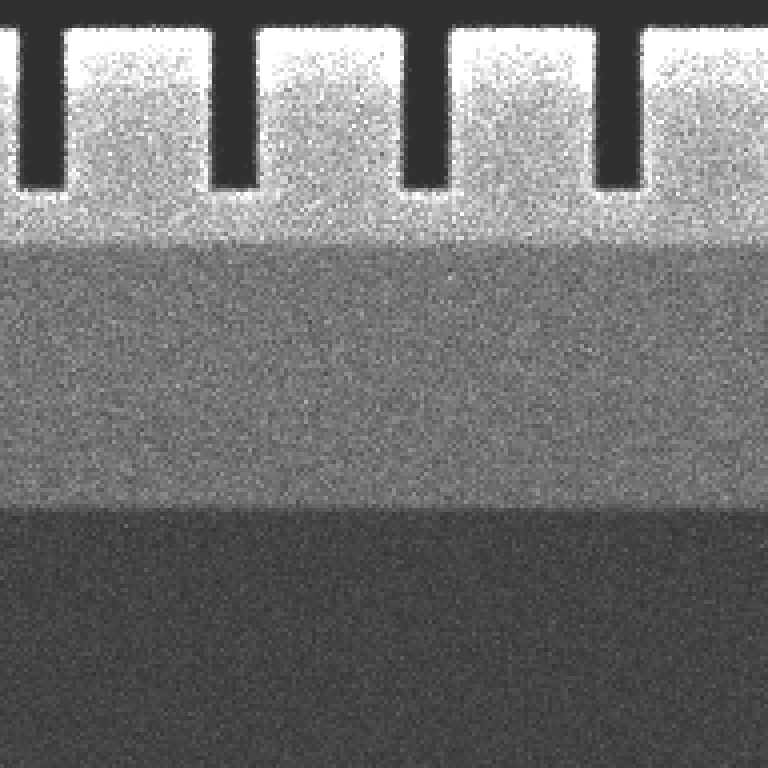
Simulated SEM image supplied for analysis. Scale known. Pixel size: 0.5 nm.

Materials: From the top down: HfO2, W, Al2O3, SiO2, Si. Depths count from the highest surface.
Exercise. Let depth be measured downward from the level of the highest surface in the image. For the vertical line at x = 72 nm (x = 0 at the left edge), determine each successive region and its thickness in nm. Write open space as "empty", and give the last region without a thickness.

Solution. HfO2 26, W 80, Al2O3 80, SiO2 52, Si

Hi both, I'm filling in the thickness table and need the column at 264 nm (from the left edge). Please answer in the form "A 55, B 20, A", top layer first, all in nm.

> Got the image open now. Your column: HfO2 26, W 80, Al2O3 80, SiO2 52, Si